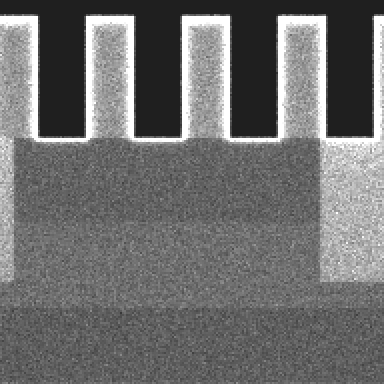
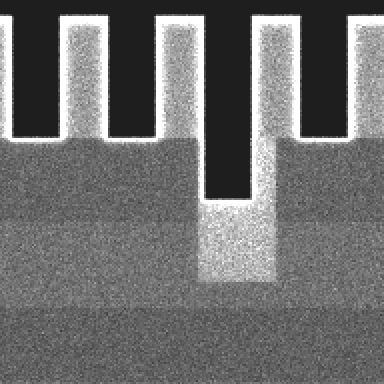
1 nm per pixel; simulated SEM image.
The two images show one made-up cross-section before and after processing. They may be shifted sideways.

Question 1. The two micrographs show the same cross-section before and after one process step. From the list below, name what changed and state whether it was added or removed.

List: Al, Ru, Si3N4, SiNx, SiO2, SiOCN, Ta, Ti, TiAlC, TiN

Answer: Ru, removed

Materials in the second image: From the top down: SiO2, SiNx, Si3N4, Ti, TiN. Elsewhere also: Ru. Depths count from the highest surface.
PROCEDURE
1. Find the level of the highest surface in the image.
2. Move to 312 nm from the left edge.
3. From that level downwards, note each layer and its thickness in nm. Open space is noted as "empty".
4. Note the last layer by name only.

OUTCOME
empty 122, SiNx 84, Si3N4 86, Ti 74, TiN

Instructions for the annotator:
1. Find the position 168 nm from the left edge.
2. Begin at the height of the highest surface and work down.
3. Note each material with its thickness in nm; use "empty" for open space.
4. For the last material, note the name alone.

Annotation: SiO2 122, SiNx 84, Si3N4 86, Ti 74, TiN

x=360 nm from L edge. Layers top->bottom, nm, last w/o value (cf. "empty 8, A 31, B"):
SiO2 122, SiNx 84, Si3N4 86, Ti 74, TiN